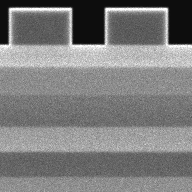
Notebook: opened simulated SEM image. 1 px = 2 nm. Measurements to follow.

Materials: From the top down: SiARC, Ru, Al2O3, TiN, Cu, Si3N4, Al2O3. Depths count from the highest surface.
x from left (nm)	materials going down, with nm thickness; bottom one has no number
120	SiARC 74, Ru 44, Al2O3 56, TiN 64, Cu 50, Si3N4 50, Al2O3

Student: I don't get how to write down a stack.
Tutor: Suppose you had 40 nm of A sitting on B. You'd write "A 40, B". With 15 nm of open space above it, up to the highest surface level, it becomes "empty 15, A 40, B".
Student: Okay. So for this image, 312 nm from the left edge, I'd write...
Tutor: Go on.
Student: SiARC 74, Ru 44, Al2O3 56, TiN 64, Cu 50, Si3N4 50, Al2O3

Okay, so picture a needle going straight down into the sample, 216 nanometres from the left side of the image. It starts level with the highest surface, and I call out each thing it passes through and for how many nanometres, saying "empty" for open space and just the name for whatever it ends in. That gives SiARC 74, Ru 44, Al2O3 56, TiN 64, Cu 50, Si3N4 50, Al2O3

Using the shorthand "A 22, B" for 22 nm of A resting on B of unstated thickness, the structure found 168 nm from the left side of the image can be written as empty 74, Ru 44, Al2O3 56, TiN 64, Cu 50, Si3N4 50, Al2O3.